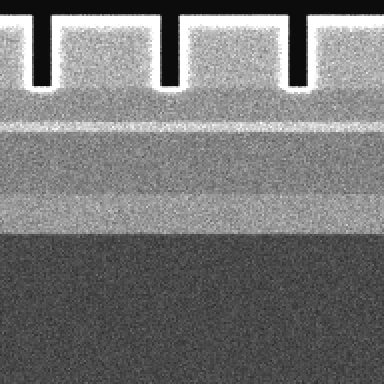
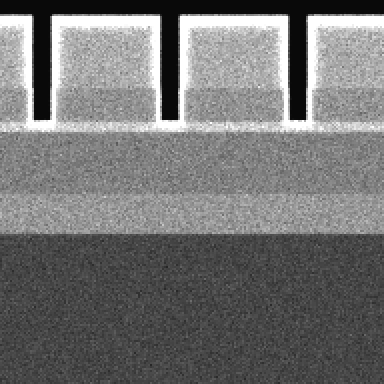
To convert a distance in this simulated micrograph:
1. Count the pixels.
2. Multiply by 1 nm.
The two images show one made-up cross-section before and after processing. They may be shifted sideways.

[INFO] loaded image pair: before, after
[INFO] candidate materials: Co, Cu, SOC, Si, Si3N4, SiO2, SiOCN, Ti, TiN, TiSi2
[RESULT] removed TiN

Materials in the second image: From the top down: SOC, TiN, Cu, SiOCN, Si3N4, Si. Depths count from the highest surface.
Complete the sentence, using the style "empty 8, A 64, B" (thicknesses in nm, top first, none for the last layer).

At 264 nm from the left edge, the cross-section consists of SOC 72, TiN 34, Cu 10, SiOCN 62, Si3N4 40, Si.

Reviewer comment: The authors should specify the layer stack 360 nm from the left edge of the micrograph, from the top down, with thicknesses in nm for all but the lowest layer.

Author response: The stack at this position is SOC 72, TiN 34, Cu 10, SiOCN 62, Si3N4 40, Si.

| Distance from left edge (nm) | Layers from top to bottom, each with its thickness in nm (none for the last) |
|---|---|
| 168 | empty 106, Cu 10, SiOCN 62, Si3N4 40, Si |